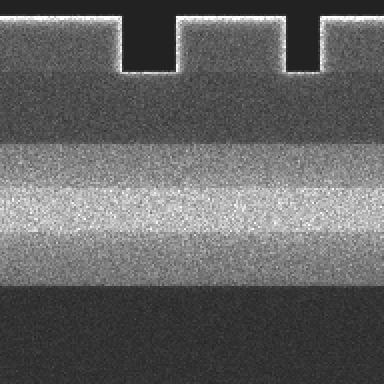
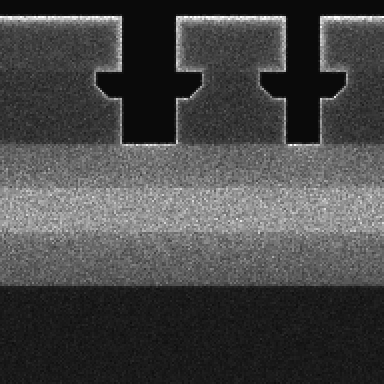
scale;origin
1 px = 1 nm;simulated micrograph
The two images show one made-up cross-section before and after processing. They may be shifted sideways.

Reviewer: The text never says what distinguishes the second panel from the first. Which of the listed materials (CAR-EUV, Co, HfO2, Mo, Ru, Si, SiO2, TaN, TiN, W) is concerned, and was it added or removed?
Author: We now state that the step removed TiN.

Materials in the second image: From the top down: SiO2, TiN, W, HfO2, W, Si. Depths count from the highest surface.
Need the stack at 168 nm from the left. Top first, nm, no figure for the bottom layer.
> empty 128, W 44, HfO2 44, W 54, Si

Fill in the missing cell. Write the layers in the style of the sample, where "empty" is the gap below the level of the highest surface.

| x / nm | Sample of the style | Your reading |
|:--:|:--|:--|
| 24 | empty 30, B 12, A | SiO2 56, TiN 72, W 44, HfO2 44, W 54, Si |